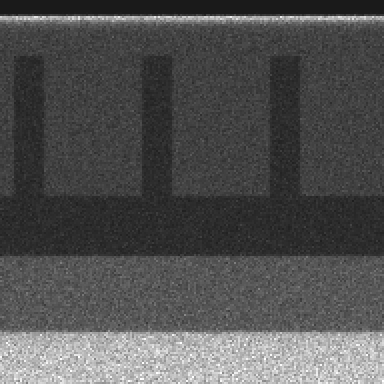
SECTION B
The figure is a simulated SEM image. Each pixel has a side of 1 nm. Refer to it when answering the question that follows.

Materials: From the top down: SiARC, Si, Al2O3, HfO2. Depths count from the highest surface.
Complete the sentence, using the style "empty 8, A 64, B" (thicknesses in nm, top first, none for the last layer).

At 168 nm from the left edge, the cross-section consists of SiARC 40, Si 200, Al2O3 76, HfO2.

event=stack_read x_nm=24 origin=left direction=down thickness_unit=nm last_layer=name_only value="SiARC 40, Si 200, Al2O3 76, HfO2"